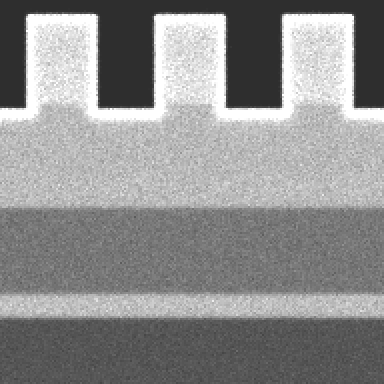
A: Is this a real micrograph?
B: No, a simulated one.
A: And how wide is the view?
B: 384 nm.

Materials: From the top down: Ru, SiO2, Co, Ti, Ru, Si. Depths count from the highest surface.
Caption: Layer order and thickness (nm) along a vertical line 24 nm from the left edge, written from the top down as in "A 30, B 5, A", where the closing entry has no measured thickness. empty 94, SiO2 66, Co 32, Ti 86, Ru 24, Si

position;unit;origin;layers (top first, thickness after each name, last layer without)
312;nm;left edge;Ru 88, SiO2 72, Co 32, Ti 86, Ru 24, Si